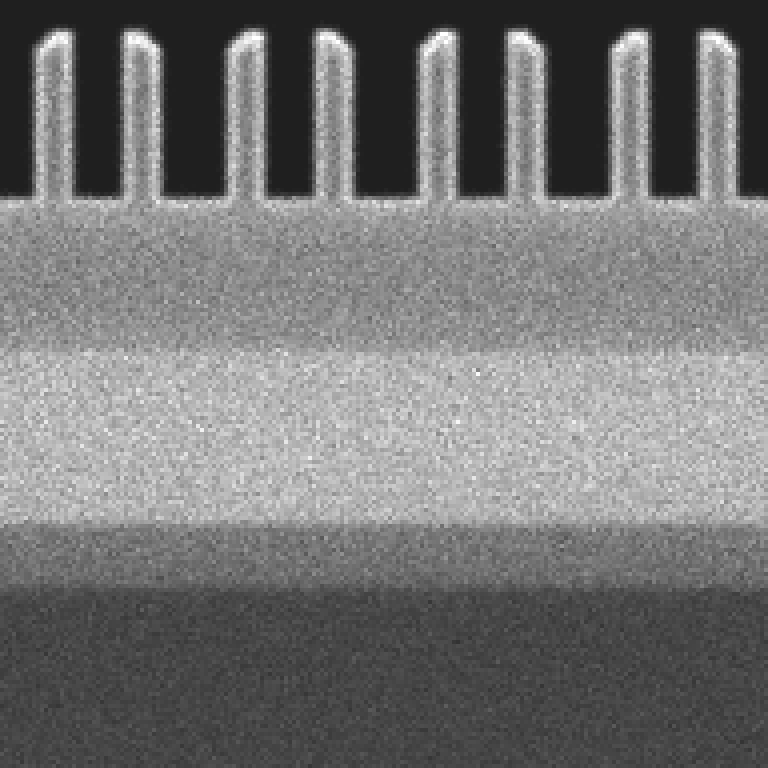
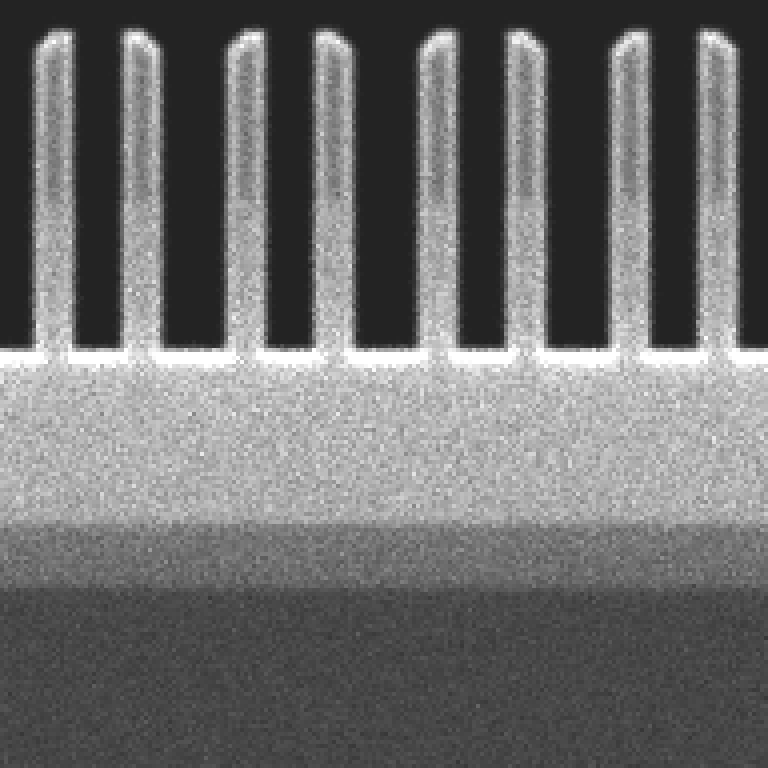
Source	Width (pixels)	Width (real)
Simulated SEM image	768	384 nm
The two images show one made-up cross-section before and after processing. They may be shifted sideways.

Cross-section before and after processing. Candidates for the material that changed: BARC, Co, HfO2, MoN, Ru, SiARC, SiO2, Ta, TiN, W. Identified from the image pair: W (removed).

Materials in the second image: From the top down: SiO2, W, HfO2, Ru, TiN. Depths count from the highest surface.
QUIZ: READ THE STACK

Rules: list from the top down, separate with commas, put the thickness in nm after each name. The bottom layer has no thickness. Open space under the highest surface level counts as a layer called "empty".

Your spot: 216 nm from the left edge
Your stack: empty 2, SiO2 82, W 76, HfO2 86, Ru 32, TiN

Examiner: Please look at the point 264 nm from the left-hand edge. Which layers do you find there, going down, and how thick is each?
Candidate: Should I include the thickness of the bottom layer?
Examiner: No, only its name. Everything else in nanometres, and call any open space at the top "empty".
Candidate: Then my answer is empty 2, SiO2 82, W 76, HfO2 86, Ru 32, TiN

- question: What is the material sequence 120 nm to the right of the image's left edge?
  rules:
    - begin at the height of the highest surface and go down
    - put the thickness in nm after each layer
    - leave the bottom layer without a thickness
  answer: empty 2, SiO2 82, W 76, HfO2 86, Ru 32, TiN